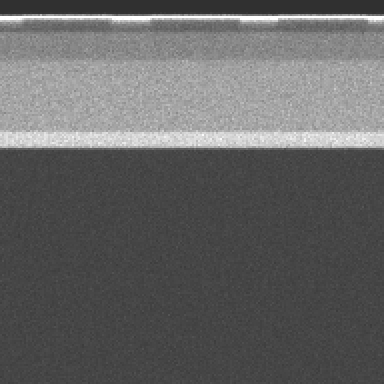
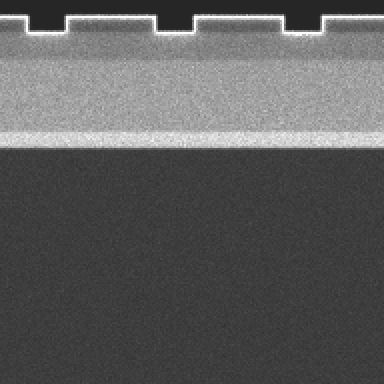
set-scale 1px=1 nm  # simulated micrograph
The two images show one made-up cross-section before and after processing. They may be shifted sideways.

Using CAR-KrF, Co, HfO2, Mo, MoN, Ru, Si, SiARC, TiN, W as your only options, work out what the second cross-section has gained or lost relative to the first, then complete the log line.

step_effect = removed SiARC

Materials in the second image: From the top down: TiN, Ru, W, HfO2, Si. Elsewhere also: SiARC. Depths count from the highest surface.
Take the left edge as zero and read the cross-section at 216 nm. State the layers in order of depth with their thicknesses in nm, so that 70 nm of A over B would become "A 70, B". TiN 16, Ru 28, W 72, HfO2 16, Si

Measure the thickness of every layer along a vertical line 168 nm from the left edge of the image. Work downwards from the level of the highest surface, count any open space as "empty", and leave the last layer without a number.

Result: empty 16, Ru 28, W 72, HfO2 16, Si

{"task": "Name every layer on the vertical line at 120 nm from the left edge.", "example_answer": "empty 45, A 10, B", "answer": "TiN 16, Ru 28, W 72, HfO2 16, Si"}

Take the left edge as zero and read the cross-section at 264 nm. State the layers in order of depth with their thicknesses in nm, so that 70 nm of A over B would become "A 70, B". TiN 16, Ru 28, W 72, HfO2 16, Si